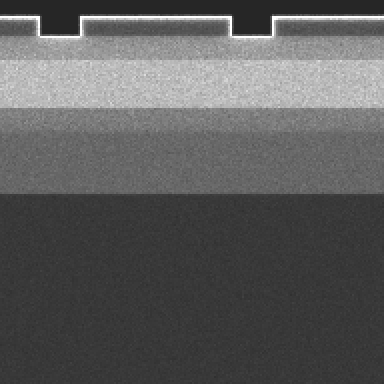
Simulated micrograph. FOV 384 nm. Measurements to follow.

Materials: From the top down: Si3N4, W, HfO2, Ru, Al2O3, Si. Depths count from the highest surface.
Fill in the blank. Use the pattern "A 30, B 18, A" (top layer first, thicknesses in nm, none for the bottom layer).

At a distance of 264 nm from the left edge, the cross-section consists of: empty 20, W 24, HfO2 48, Ru 24, Al2O3 62, Si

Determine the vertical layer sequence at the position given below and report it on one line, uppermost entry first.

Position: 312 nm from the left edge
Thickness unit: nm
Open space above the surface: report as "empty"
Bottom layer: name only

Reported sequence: Si3N4 20, W 24, HfO2 48, Ru 24, Al2O3 62, Si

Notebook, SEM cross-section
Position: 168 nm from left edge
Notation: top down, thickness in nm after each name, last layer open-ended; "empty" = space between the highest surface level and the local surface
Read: Si3N4 20, W 24, HfO2 48, Ru 24, Al2O3 62, Si